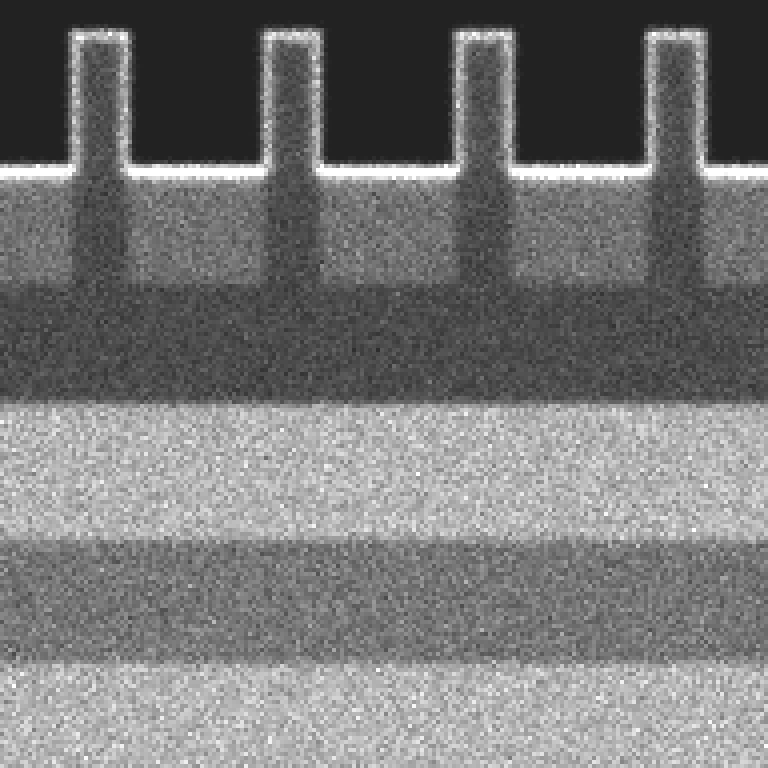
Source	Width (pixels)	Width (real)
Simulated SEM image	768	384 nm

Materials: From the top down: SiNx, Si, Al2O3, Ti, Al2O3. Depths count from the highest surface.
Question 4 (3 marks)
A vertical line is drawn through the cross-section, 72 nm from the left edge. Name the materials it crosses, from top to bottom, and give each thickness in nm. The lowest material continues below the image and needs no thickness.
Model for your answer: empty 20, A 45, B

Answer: empty 68, SiNx 58, Si 60, Al2O3 68, Ti 62, Al2O3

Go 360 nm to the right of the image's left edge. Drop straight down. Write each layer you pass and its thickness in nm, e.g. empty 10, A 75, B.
empty 68, SiNx 58, Si 60, Al2O3 68, Ti 62, Al2O3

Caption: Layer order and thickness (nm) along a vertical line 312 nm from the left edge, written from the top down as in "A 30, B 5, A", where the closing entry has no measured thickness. empty 68, SiNx 58, Si 60, Al2O3 68, Ti 62, Al2O3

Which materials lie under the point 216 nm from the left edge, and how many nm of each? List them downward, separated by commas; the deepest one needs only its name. empty 68, SiNx 58, Si 60, Al2O3 68, Ti 62, Al2O3